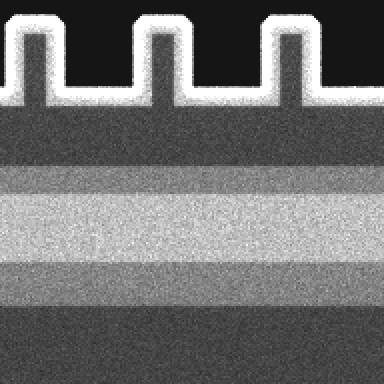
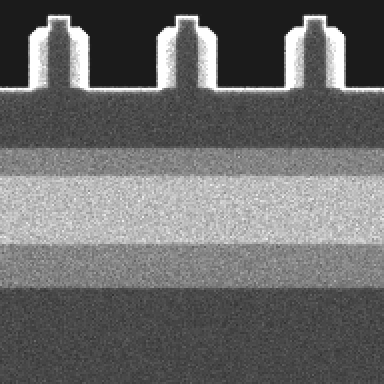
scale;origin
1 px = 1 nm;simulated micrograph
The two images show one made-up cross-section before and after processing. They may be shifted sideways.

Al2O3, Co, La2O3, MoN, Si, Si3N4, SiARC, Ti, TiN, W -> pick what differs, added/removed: Al2O3 removed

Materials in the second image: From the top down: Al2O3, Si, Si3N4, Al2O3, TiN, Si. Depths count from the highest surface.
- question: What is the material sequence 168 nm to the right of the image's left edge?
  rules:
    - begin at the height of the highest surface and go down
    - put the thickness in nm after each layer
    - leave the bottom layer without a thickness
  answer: empty 12, Al2O3 60, Si 60, Si3N4 28, Al2O3 68, TiN 44, Si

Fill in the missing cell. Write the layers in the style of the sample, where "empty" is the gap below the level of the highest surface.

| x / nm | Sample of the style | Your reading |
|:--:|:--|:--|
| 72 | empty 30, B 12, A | empty 12, Al2O3 60, Si 60, Si3N4 28, Al2O3 68, TiN 44, Si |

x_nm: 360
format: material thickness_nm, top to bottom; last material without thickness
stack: empty 72, Si 60, Si3N4 28, Al2O3 68, TiN 44, Si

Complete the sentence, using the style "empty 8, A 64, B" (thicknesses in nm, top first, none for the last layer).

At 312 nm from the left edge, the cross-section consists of Si 132, Si3N4 28, Al2O3 68, TiN 44, Si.